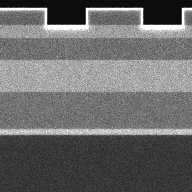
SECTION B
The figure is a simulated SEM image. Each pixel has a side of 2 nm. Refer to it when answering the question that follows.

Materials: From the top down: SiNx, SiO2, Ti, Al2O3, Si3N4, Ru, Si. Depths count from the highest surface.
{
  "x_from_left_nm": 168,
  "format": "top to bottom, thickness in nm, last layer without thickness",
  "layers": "empty 34, SiO2 26, Ti 44, Al2O3 64, Si3N4 74, Ru 12, Si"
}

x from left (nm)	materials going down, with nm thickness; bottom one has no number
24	SiNx 34, SiO2 26, Ti 44, Al2O3 64, Si3N4 74, Ru 12, Si